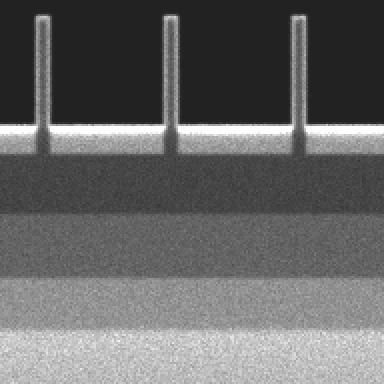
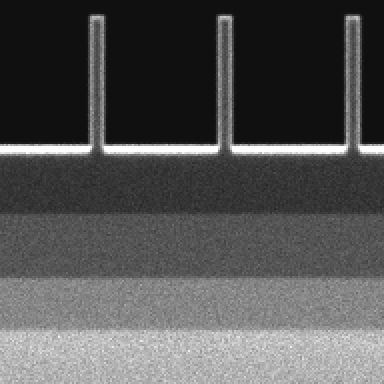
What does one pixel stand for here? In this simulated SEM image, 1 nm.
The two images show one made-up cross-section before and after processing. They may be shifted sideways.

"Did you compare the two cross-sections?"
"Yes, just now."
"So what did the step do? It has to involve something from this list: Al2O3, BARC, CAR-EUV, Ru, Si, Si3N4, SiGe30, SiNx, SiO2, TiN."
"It removed Al2O3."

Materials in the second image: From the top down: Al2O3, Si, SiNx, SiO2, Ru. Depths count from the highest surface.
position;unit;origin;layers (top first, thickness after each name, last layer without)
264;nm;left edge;empty 130, Al2O3 8, Si 60, SiNx 64, SiO2 52, Ru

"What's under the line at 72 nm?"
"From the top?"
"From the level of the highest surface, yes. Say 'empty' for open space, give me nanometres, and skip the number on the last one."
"empty 130, Al2O3 8, Si 60, SiNx 64, SiO2 52, Ru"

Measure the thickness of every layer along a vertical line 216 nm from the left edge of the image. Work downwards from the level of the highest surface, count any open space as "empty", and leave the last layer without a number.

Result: empty 130, Al2O3 8, Si 60, SiNx 64, SiO2 52, Ru